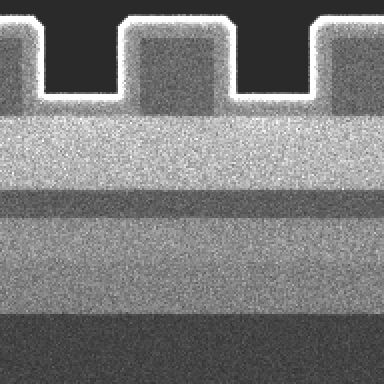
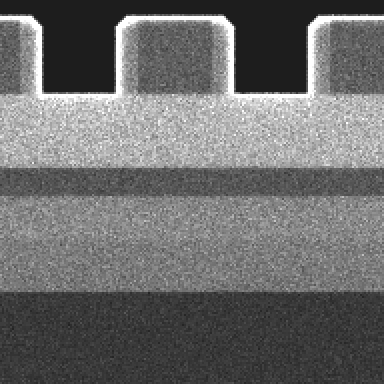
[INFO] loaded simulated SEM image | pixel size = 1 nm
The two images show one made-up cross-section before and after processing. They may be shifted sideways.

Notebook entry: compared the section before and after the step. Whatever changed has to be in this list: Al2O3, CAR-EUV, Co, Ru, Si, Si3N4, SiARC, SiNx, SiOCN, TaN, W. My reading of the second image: Al2O3 removed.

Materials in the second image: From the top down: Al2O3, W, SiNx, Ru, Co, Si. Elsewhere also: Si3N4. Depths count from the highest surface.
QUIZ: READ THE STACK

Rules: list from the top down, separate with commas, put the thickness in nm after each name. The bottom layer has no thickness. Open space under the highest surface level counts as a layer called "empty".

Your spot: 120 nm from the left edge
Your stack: empty 6, Al2O3 72, W 74, SiNx 28, Ru 44, Co 52, Si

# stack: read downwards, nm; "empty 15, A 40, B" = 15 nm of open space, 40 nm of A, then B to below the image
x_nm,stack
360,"Si3N4 78, W 74, SiNx 28, Ru 44, Co 52, Si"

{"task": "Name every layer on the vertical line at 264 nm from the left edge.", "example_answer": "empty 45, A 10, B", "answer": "empty 78, W 74, SiNx 28, Ru 44, Co 52, Si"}